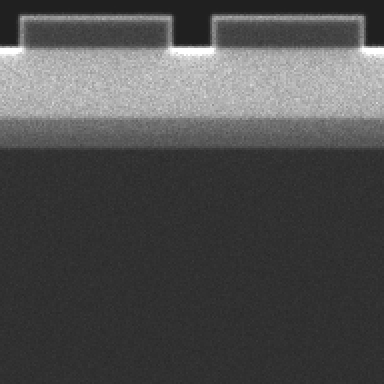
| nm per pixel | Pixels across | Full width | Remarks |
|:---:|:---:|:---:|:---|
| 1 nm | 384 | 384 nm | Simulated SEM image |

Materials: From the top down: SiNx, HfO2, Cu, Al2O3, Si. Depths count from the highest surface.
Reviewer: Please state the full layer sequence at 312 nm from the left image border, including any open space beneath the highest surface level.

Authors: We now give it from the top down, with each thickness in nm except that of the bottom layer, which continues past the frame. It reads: SiNx 32, HfO2 70, Cu 16, Al2O3 14, Si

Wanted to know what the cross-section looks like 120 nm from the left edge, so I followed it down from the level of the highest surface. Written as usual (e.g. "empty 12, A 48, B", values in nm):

SiNx 32, HfO2 70, Cu 16, Al2O3 14, Si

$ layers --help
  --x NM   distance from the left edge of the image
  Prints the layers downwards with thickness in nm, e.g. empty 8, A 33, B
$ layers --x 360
SiNx 32, HfO2 70, Cu 16, Al2O3 14, Si